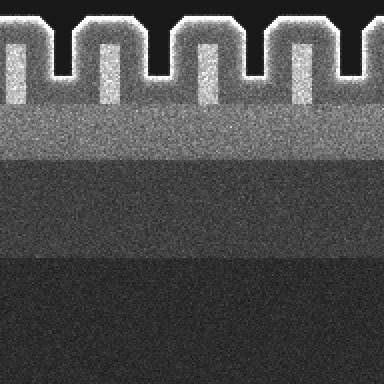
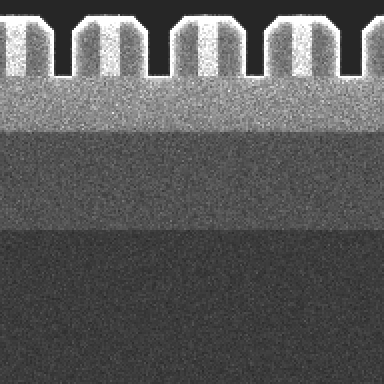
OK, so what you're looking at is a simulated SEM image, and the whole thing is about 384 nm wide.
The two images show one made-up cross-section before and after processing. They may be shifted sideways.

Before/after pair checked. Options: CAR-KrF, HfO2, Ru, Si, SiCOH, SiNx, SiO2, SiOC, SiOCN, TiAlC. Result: removed SiO2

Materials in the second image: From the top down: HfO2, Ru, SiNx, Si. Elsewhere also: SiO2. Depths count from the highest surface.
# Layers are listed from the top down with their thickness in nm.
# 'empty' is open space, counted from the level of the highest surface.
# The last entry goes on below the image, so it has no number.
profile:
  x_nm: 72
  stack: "empty 14, SiO2 46, Ru 56, SiNx 98, Si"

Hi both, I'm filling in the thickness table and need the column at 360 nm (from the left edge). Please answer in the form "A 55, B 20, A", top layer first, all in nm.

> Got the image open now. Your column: empty 60, Ru 56, SiNx 98, Si